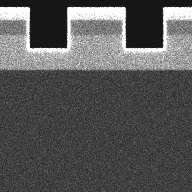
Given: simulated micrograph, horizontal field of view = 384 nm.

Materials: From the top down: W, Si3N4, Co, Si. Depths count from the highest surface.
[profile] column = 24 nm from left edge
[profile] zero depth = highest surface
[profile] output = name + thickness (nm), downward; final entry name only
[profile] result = W 24, Si3N4 30, Co 70, Si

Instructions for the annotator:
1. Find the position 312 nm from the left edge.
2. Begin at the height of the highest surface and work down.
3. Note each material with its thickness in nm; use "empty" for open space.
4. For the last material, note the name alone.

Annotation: empty 82, Co 42, Si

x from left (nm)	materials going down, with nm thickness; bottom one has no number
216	W 24, Si3N4 30, Co 70, Si